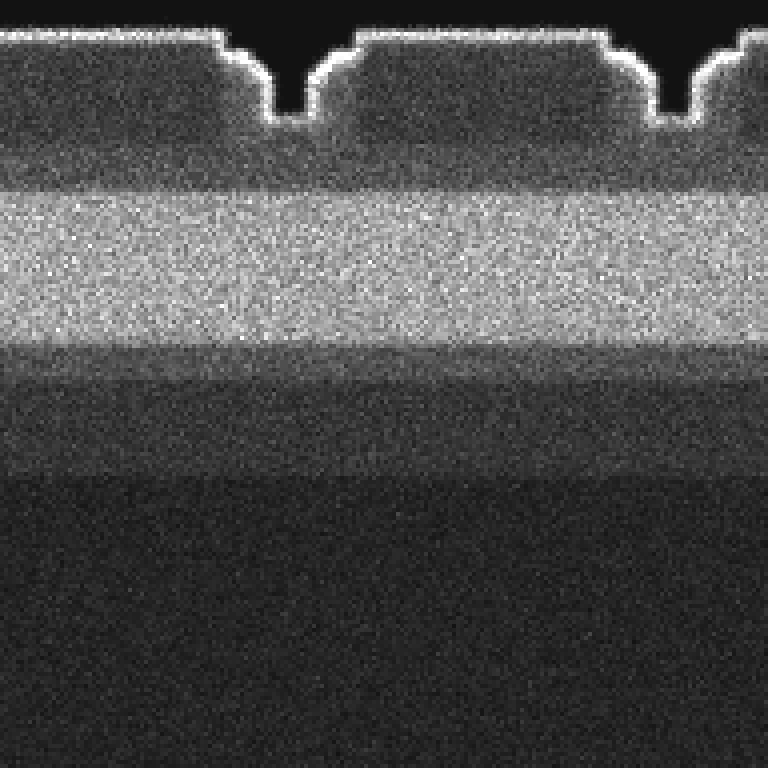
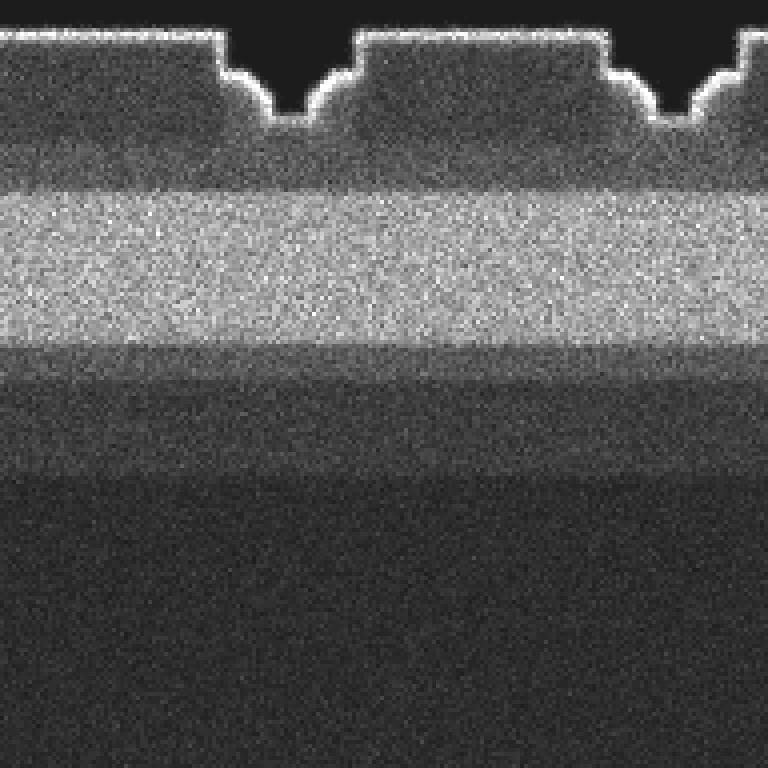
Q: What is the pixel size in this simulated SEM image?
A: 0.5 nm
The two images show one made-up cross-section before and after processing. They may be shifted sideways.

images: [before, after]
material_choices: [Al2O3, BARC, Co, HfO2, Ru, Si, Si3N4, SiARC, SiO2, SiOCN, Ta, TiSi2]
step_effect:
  removed: Al2O3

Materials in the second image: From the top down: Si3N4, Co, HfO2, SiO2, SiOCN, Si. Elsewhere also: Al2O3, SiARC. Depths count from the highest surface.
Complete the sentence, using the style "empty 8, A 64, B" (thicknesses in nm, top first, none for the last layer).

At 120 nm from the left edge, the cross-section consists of empty 20, Al2O3 36, Co 24, HfO2 76, SiO2 18, SiOCN 48, Si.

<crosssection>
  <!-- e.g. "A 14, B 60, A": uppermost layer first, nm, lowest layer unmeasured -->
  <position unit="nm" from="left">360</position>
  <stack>empty 20, Al2O3 36, Co 24, HfO2 76, SiO2 18, SiOCN 48, Si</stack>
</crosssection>